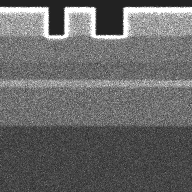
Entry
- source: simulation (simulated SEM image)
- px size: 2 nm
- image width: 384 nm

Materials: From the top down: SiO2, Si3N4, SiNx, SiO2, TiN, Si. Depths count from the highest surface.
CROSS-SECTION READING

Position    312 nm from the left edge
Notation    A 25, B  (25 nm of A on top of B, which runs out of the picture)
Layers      SiO2 56, Si3N4 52, SiNx 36, SiO2 14, TiN 78, Si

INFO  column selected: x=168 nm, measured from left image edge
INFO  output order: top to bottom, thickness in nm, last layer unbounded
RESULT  SiO2 56, Si3N4 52, SiNx 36, SiO2 14, TiN 78, Si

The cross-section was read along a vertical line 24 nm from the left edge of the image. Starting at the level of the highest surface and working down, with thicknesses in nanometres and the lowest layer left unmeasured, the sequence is SiO2 56, Si3N4 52, SiNx 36, SiO2 14, TiN 78, Si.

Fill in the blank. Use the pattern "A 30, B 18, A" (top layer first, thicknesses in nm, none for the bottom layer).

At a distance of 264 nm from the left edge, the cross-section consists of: SiO2 56, Si3N4 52, SiNx 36, SiO2 14, TiN 78, Si